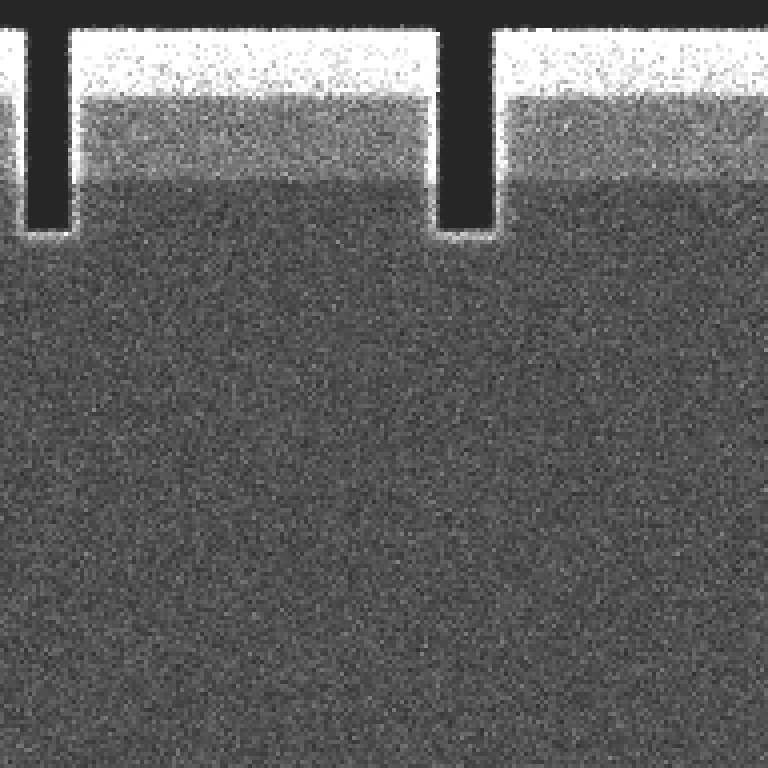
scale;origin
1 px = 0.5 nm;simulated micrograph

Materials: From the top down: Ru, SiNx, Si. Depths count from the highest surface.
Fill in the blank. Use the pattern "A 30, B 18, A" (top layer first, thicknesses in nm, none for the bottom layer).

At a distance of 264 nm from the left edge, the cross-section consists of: Ru 32, SiNx 42, Si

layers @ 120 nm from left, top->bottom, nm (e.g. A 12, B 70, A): Ru 32, SiNx 42, Si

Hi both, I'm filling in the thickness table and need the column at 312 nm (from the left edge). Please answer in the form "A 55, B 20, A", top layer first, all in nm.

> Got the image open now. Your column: Ru 32, SiNx 42, Si